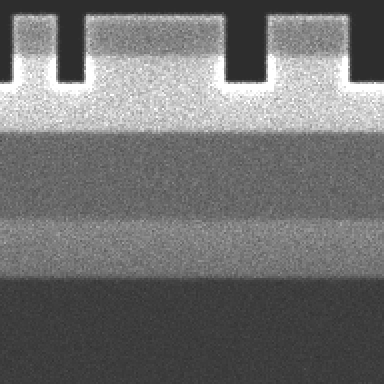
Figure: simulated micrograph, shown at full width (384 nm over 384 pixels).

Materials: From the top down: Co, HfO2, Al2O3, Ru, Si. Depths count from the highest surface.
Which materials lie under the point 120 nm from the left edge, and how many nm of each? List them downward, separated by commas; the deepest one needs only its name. Co 40, HfO2 76, Al2O3 88, Ru 58, Si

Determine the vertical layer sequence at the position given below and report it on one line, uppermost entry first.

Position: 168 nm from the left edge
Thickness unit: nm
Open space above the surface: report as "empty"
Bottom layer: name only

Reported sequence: Co 40, HfO2 76, Al2O3 88, Ru 58, Si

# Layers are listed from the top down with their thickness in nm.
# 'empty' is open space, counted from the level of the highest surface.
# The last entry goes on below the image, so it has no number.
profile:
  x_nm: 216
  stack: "Co 40, HfO2 76, Al2O3 88, Ru 58, Si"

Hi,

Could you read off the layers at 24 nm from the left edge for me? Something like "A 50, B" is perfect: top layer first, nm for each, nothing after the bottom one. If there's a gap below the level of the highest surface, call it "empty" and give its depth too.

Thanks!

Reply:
Co 40, HfO2 76, Al2O3 88, Ru 58, Si